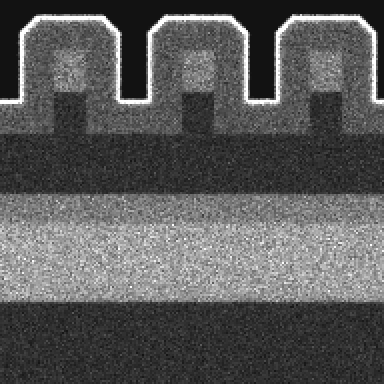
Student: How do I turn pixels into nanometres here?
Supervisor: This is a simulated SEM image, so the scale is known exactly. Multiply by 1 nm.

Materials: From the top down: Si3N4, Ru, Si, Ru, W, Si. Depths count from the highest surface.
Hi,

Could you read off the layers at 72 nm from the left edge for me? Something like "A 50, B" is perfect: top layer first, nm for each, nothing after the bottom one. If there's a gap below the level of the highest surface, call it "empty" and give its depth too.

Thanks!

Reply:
Si3N4 34, Ru 42, Si 102, Ru 30, W 78, Si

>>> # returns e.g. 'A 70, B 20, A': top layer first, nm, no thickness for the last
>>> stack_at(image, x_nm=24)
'empty 12, Si3N4 106, Si 60, Ru 30, W 78, Si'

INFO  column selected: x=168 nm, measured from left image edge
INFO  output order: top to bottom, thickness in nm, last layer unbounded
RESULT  Si3N4 118, Si 60, Ru 30, W 78, Si